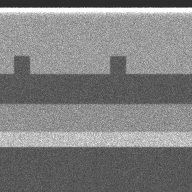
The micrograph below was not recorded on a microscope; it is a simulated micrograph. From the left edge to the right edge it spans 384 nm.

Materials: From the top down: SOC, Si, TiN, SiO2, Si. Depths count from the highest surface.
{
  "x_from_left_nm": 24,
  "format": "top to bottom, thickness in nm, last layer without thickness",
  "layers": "SOC 132, Si 60, TiN 56, SiO2 30, Si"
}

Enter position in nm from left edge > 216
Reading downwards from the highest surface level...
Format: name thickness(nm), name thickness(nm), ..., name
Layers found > SOC 132, Si 60, TiN 56, SiO2 30, Si